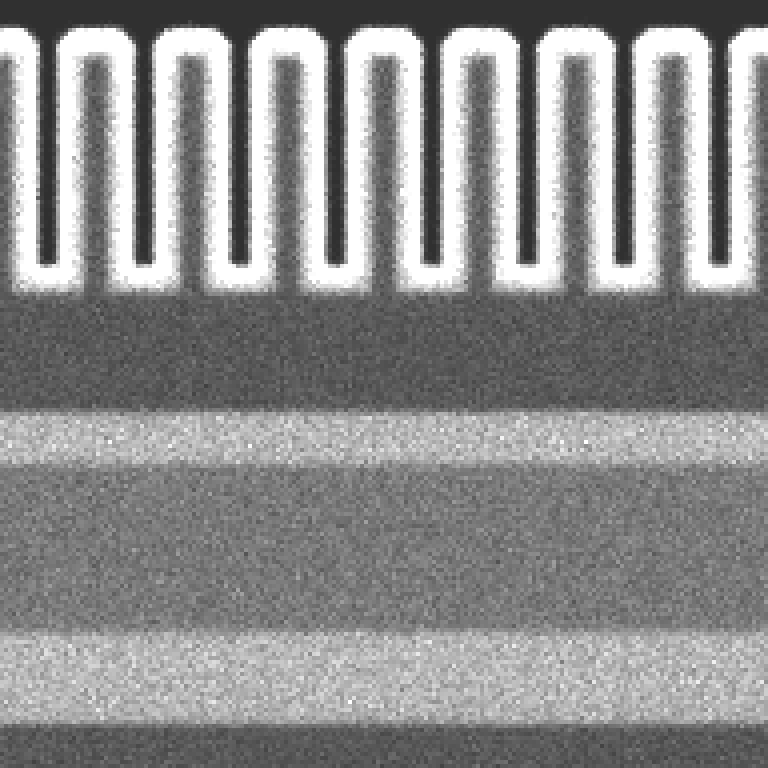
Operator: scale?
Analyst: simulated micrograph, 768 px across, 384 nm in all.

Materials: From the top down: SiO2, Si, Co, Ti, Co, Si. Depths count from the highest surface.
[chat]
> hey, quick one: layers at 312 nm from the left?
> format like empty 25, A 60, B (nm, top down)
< empty 118, SiO2 12, Si 60, Co 26, Ti 84, Co 46, Si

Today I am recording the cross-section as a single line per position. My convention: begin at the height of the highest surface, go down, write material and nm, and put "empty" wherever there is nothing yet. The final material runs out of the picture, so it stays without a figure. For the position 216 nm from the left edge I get empty 118, SiO2 12, Si 60, Co 26, Ti 84, Co 46, Si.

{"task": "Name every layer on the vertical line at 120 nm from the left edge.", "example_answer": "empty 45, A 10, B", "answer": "empty 118, SiO2 12, Si 60, Co 26, Ti 84, Co 46, Si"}